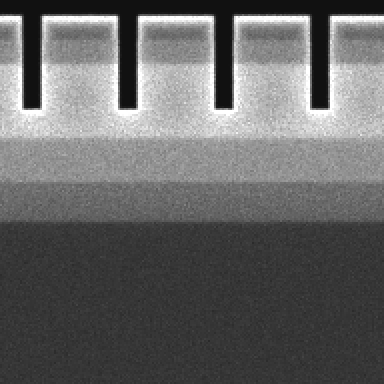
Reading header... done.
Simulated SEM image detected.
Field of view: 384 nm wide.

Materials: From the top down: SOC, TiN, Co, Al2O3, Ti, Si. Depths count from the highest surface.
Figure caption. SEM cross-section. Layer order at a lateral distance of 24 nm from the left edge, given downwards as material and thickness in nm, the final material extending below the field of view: empty 94, Co 28, Al2O3 44, Ti 40, Si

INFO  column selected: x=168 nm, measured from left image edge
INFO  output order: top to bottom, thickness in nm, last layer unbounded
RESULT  SOC 24, TiN 24, Co 74, Al2O3 44, Ti 40, Si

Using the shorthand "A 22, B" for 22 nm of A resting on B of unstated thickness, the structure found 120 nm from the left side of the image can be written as empty 94, Co 28, Al2O3 44, Ti 40, Si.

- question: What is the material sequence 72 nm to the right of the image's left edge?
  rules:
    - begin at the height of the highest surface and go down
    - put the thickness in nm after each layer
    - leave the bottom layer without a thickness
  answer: SOC 24, TiN 24, Co 74, Al2O3 44, Ti 40, Si